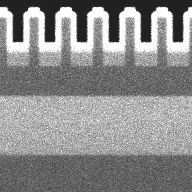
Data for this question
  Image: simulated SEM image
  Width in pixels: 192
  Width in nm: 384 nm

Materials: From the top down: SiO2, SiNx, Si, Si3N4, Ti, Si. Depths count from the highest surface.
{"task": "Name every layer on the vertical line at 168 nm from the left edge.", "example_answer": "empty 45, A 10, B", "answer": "empty 70, SiO2 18, SiNx 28, Si 60, Si3N4 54, Ti 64, Si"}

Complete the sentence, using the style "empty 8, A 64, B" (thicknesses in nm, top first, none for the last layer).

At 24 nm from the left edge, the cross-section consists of empty 70, SiO2 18, SiNx 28, Si 60, Si3N4 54, Ti 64, Si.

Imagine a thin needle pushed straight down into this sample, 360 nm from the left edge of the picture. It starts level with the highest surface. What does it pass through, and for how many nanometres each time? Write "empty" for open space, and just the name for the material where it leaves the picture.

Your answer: empty 70, SiO2 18, SiNx 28, Si 60, Si3N4 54, Ti 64, Si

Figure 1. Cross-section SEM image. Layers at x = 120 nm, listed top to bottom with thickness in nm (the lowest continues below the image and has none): empty 8, SiO2 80, SiNx 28, Si 60, Si3N4 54, Ti 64, Si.